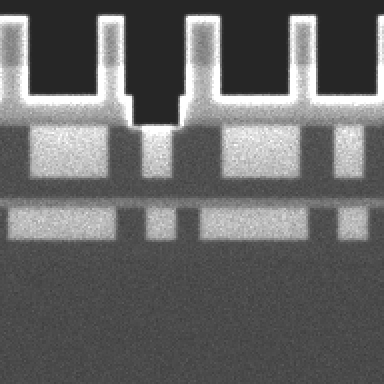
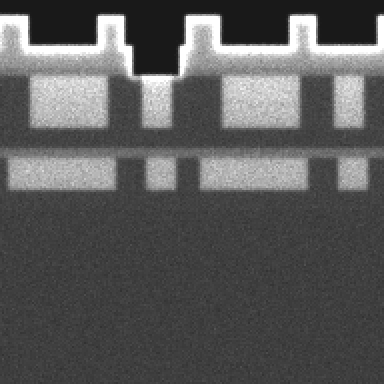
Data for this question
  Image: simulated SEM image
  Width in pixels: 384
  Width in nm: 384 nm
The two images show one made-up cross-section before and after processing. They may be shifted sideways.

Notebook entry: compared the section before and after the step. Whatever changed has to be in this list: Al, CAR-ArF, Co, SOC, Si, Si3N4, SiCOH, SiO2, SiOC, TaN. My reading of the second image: SOC removed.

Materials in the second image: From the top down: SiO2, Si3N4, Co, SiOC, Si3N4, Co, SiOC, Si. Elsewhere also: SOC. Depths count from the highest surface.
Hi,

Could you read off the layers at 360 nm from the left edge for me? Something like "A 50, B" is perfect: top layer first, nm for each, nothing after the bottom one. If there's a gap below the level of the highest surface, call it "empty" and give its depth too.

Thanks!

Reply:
empty 30, SiO2 22, Si3N4 8, Co 52, SiOC 20, Si3N4 10, Co 32, SiOC 20, Si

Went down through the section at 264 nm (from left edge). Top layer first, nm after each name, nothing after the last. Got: empty 30, SiO2 22, Si3N4 8, Co 52, SiOC 20, Si3N4 10, Co 32, SiOC 20, Si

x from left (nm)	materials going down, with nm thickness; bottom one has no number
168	empty 60, Co 52, SiOC 20, Si3N4 10, Co 32, SiOC 20, Si